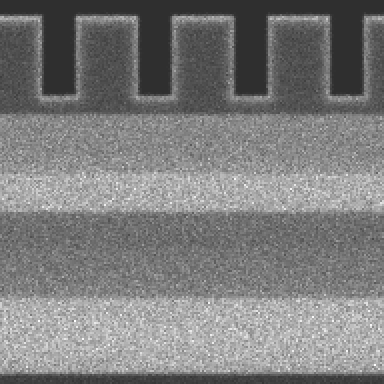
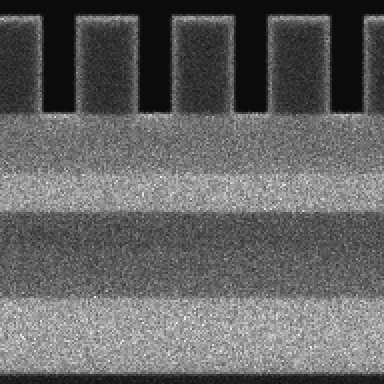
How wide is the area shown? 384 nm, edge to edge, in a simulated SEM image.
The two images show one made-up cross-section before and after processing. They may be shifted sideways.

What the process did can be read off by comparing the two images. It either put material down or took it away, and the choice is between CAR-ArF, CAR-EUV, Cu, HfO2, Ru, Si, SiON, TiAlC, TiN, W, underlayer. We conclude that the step removed underlayer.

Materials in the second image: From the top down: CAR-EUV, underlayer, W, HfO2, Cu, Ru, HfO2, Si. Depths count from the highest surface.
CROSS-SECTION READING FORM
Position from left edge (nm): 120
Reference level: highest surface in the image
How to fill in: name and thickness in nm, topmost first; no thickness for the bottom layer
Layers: CAR-EUV 80, underlayer 18, W 60, HfO2 38, Cu 36, Ru 50, HfO2 76, Si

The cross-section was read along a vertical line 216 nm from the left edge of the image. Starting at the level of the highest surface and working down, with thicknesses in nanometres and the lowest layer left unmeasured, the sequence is CAR-EUV 80, underlayer 18, W 60, HfO2 38, Cu 36, Ru 50, HfO2 76, Si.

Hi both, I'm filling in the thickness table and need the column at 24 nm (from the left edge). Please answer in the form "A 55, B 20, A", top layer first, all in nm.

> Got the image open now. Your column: CAR-EUV 80, underlayer 18, W 60, HfO2 38, Cu 36, Ru 50, HfO2 76, Si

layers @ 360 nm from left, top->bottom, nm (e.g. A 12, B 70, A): empty 98, W 60, HfO2 38, Cu 36, Ru 50, HfO2 76, Si